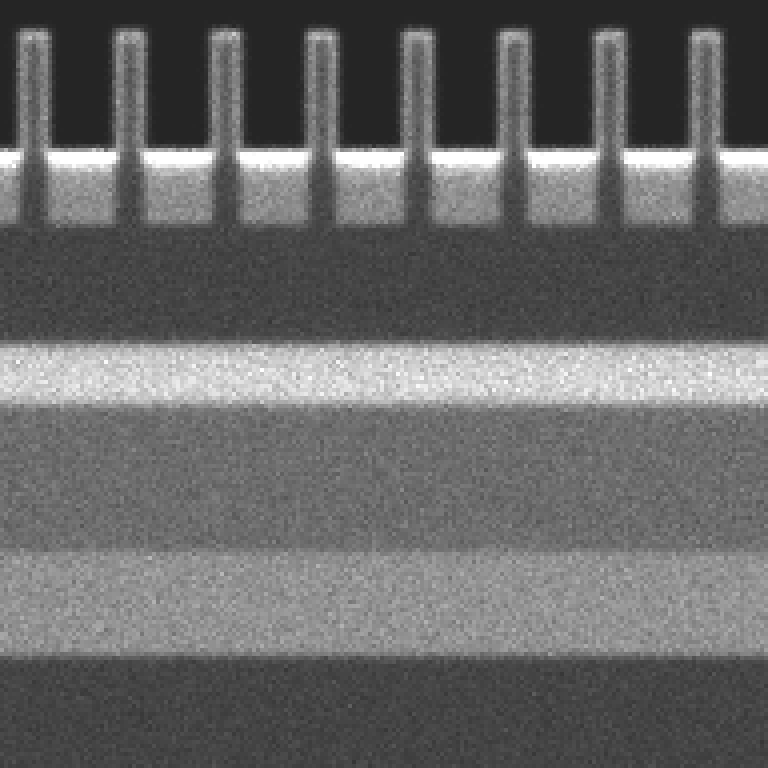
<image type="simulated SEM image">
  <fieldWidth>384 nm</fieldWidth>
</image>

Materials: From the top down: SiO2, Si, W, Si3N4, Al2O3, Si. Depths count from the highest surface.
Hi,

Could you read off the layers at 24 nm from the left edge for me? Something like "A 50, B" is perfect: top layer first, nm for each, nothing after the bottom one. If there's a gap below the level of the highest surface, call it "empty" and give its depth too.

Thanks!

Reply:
empty 60, SiO2 36, Si 60, W 30, Si3N4 74, Al2O3 52, Si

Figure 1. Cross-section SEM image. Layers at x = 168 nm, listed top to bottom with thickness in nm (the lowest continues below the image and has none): empty 60, SiO2 36, Si 60, W 30, Si3N4 74, Al2O3 52, Si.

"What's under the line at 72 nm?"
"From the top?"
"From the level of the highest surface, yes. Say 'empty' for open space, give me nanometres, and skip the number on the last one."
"empty 60, SiO2 36, Si 60, W 30, Si3N4 74, Al2O3 52, Si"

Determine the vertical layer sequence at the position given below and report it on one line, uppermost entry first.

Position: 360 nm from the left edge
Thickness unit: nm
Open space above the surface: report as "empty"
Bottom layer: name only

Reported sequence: empty 60, SiO2 36, Si 60, W 30, Si3N4 74, Al2O3 52, Si